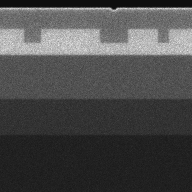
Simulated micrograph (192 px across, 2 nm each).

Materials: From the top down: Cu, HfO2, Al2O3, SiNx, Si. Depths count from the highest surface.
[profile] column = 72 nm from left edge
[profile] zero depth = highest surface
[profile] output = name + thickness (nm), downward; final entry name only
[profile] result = Cu 70, HfO2 24, Al2O3 88, SiNx 72, Si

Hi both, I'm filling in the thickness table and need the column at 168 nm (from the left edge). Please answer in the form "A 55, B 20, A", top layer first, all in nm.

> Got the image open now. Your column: Cu 42, HfO2 52, Al2O3 88, SiNx 72, Si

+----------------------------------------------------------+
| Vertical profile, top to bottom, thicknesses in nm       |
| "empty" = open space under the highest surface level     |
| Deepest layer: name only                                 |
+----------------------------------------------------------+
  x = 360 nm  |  Cu 42, HfO2 52, Al2O3 88, SiNx 72, Si